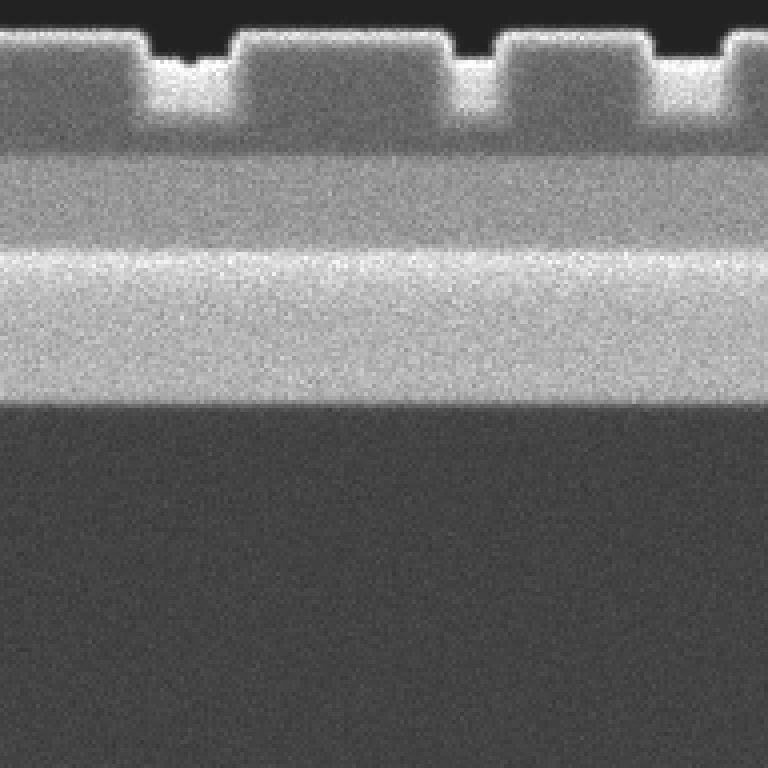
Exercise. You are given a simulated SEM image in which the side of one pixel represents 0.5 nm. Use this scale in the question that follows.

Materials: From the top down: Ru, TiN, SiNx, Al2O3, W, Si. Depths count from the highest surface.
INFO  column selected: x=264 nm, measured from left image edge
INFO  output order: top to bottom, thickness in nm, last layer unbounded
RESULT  TiN 8, SiNx 54, Al2O3 48, W 76, Si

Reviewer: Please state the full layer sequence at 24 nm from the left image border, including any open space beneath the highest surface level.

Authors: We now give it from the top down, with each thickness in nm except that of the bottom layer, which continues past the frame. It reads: TiN 8, SiNx 54, Al2O3 48, W 76, Si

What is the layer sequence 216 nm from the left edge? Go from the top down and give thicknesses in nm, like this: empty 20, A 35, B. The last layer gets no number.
TiN 8, SiNx 54, Al2O3 48, W 76, Si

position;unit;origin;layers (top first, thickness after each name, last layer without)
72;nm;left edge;empty 4, TiN 44, SiNx 14, Al2O3 48, W 76, Si